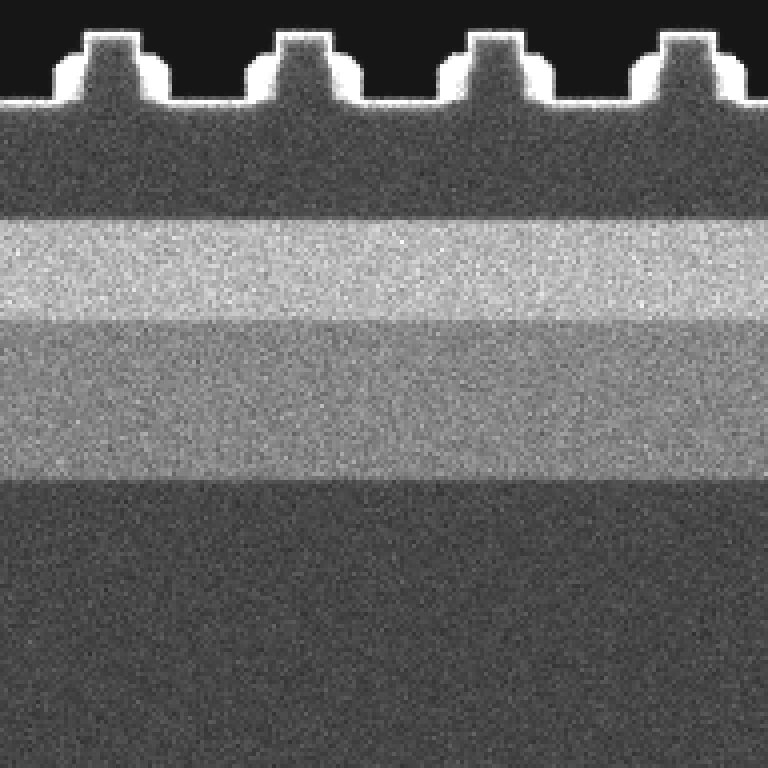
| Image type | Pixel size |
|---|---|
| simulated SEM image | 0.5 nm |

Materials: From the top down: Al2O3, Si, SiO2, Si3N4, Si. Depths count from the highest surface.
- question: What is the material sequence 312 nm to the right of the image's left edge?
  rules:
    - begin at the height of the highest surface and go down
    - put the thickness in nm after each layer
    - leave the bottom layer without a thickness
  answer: empty 34, Si 60, SiO2 50, Si3N4 80, Si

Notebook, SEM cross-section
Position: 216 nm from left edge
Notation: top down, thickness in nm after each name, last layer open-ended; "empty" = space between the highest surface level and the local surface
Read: empty 34, Si 60, SiO2 50, Si3N4 80, Si